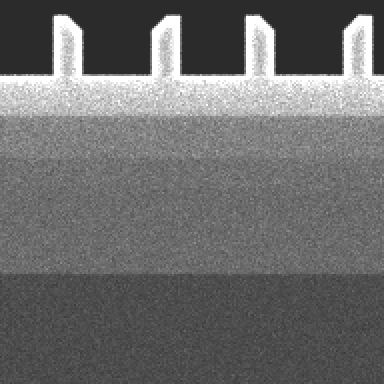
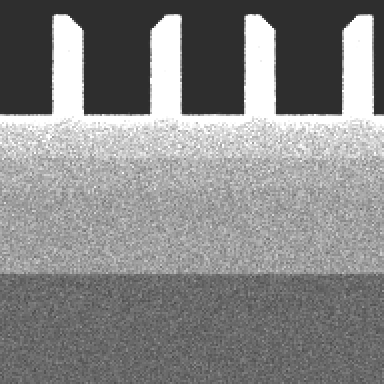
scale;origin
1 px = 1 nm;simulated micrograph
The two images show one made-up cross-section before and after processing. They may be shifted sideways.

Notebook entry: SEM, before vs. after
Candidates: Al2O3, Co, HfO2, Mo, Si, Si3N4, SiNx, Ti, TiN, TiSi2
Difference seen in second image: Co removed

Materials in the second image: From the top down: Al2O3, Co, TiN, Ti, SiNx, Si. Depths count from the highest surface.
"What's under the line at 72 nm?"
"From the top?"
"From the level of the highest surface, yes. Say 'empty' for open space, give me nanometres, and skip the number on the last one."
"empty 6, Al2O3 54, Co 40, TiN 42, Ti 32, SiNx 84, Si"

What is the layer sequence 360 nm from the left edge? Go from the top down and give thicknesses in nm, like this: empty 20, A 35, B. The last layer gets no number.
Al2O3 60, Co 40, TiN 42, Ti 32, SiNx 84, Si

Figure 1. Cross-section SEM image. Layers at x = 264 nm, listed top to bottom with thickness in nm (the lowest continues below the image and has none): empty 6, Al2O3 54, Co 40, TiN 42, Ti 32, SiNx 84, Si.